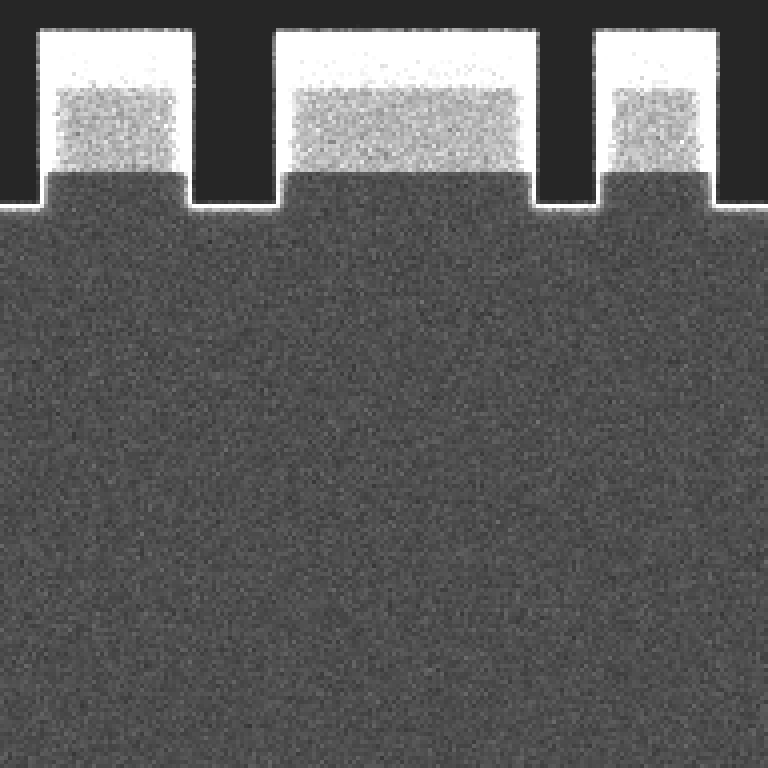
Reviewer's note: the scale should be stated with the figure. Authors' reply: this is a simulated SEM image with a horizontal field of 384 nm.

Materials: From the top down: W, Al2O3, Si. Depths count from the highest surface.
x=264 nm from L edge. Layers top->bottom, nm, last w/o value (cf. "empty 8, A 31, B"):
W 28, Al2O3 42, Si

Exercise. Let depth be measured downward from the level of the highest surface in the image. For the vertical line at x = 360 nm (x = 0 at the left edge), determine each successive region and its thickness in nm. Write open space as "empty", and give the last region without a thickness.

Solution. empty 86, Si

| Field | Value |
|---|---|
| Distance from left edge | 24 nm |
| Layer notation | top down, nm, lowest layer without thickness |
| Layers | W 28, Al2O3 42, Si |